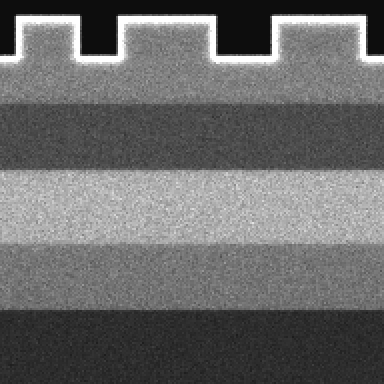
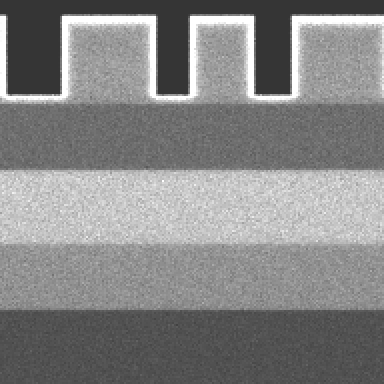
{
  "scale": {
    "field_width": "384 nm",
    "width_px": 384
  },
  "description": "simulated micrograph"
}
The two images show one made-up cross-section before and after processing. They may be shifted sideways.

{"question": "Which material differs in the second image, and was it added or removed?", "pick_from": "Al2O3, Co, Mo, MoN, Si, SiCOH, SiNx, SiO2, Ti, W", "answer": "Al2O3, removed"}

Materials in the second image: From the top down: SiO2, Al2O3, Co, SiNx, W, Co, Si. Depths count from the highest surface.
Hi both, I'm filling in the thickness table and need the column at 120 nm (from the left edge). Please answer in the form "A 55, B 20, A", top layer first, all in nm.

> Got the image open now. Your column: SiO2 40, Al2O3 40, Co 8, SiNx 66, W 74, Co 66, Si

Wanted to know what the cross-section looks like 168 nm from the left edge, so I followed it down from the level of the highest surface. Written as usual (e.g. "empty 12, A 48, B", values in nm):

empty 80, Co 8, SiNx 66, W 74, Co 66, Si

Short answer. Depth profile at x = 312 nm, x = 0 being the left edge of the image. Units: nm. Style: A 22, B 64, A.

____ SiO2 40, Al2O3 40, Co 8, SiNx 66, W 74, Co 66, Si